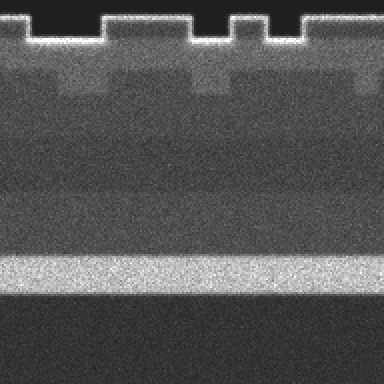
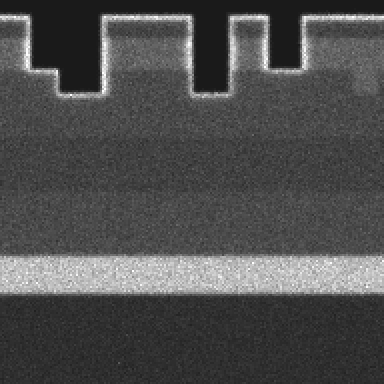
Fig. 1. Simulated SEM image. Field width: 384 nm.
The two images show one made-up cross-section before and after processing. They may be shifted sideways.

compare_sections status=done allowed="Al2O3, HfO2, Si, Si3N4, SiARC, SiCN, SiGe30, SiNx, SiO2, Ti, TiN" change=removed material="SiO2"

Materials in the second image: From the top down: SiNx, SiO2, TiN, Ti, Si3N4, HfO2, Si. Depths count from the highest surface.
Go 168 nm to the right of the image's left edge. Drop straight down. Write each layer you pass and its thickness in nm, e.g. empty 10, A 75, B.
SiNx 22, SiO2 32, TiN 68, Ti 54, Si3N4 64, HfO2 38, Si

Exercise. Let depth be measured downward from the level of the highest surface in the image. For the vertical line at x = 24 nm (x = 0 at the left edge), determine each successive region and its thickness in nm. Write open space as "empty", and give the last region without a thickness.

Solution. SiNx 22, SiO2 32, TiN 68, Ti 54, Si3N4 64, HfO2 38, Si